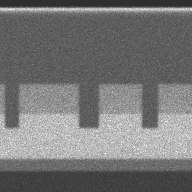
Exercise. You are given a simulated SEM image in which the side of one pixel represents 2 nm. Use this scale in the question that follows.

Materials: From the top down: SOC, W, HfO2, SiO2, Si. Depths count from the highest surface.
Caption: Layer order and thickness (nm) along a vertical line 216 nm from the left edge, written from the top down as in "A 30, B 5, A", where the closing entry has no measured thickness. SOC 152, W 60, HfO2 90, SiO2 24, Si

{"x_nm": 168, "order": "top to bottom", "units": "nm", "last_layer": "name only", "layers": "SOC 240, HfO2 62, SiO2 24, Si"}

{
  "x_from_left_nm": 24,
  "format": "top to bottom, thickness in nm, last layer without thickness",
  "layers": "SOC 240, HfO2 62, SiO2 24, Si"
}